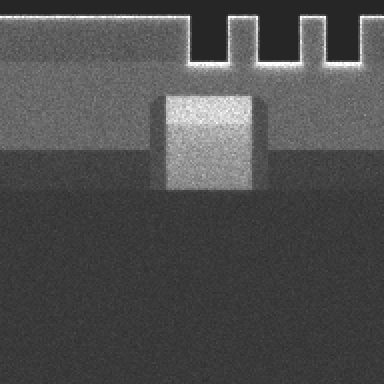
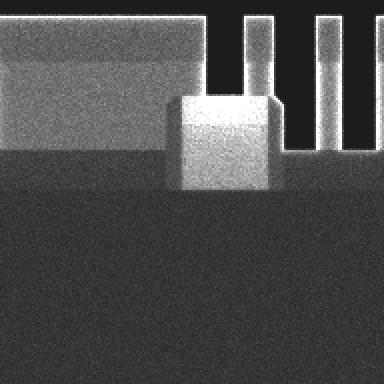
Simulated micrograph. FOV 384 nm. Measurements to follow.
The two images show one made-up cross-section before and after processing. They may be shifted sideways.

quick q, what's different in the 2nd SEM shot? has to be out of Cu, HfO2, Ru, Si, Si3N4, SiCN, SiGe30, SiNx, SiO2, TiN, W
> SiO2 removed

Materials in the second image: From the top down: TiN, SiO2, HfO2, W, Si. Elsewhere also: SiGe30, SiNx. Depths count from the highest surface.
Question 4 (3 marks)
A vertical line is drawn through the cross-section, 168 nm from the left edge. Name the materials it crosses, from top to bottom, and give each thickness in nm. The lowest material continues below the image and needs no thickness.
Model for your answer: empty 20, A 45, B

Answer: TiN 46, SiO2 40, SiNx 88, Si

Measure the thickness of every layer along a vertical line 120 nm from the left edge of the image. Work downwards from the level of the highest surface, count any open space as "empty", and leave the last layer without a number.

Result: TiN 46, SiO2 88, SiGe30 40, Si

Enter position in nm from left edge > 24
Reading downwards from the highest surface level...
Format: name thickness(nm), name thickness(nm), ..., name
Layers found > TiN 46, SiO2 88, SiGe30 40, Si